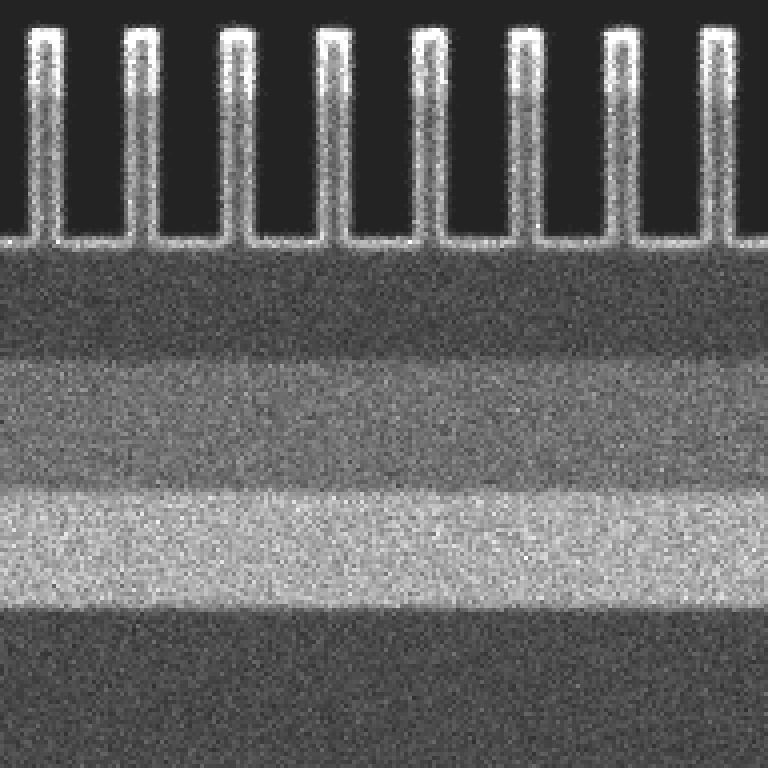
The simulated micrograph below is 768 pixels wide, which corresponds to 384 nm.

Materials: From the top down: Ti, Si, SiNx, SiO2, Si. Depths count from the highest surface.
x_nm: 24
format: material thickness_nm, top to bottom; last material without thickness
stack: Ti 32, Si 132, SiNx 66, SiO2 58, Si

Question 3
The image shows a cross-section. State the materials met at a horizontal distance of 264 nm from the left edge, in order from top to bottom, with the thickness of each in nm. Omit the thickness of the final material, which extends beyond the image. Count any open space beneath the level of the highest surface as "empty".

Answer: Ti 32, Si 132, SiNx 66, SiO2 58, Si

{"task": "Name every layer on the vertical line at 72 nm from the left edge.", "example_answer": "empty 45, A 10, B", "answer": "Ti 32, Si 132, SiNx 66, SiO2 58, Si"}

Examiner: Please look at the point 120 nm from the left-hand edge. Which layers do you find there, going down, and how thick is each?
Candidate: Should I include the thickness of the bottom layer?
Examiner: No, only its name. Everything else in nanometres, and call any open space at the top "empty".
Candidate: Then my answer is Ti 32, Si 132, SiNx 66, SiO2 58, Si